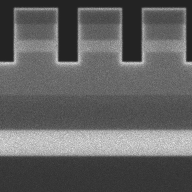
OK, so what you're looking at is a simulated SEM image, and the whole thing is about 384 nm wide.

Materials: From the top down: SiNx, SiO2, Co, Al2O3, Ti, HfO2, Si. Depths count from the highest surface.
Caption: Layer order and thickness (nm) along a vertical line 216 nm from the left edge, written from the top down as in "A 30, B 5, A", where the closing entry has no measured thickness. SiNx 32, SiO2 32, Co 24, Al2O3 86, Ti 70, HfO2 52, Si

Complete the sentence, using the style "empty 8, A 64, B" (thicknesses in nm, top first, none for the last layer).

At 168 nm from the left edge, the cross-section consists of SiNx 32, SiO2 32, Co 24, Al2O3 86, Ti 70, HfO2 52, Si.